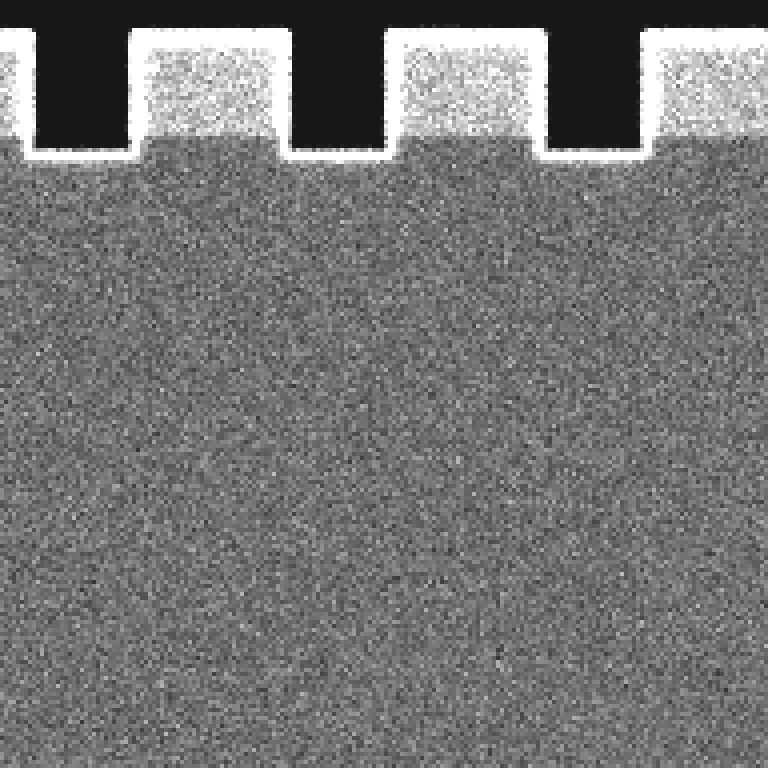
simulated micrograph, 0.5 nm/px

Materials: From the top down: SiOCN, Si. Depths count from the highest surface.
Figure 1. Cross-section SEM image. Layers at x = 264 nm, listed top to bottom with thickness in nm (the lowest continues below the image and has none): SiOCN 52, Si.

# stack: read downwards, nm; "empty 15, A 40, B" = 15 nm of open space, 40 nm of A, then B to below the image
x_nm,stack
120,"SiOCN 52, Si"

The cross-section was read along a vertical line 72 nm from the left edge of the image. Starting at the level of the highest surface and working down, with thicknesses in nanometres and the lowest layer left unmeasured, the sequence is SiOCN 52, Si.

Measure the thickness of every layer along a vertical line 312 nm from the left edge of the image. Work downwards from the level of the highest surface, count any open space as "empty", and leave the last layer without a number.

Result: empty 60, Si